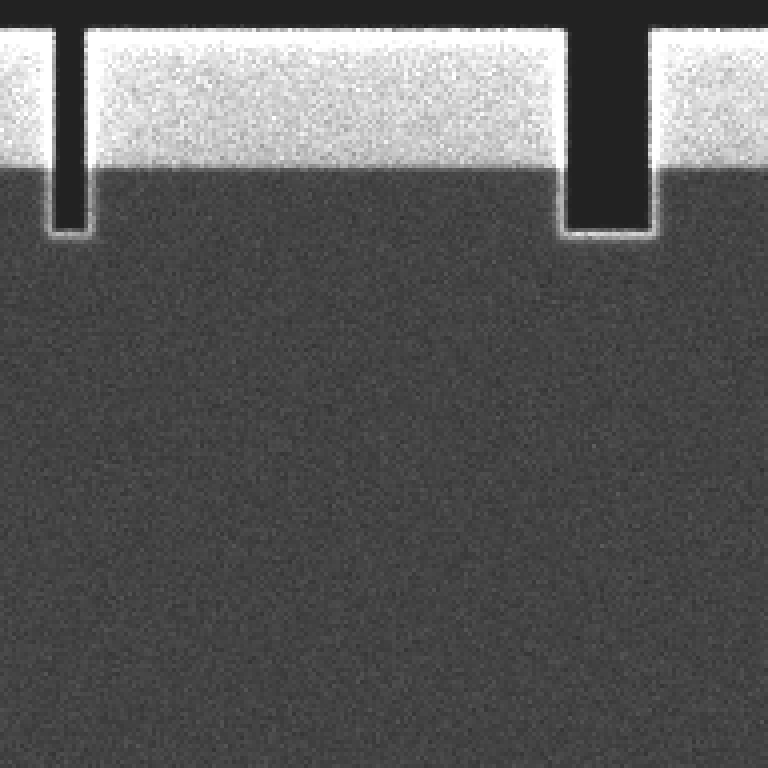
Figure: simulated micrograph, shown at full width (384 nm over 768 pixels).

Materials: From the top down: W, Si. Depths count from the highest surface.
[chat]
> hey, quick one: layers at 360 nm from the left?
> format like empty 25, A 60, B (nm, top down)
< W 68, Si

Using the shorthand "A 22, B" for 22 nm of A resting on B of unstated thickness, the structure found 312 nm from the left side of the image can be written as empty 100, Si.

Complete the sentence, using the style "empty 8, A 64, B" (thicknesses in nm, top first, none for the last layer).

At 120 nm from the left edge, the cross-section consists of W 68, Si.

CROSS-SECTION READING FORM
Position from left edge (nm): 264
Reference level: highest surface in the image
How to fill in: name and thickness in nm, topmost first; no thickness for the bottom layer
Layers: W 68, Si